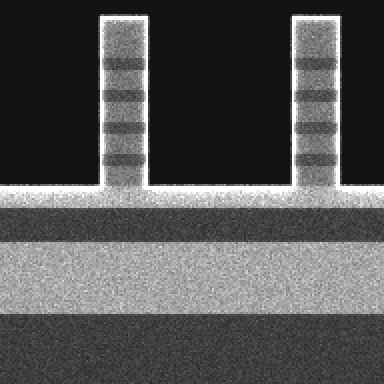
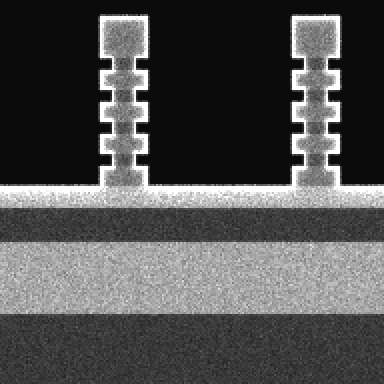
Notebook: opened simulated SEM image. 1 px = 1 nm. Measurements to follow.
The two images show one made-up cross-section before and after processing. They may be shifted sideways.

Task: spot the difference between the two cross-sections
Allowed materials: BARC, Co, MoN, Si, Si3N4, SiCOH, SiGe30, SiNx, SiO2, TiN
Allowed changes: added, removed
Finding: removed SiGe30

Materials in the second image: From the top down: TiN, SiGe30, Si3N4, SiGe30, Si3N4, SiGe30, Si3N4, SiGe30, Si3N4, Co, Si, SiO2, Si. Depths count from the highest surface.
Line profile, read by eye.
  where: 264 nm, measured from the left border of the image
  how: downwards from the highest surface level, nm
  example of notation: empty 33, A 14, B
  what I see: empty 170, Co 22, Si 34, SiO2 72, Si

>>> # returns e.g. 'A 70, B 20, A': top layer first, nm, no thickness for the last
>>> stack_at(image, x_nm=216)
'empty 170, Co 22, Si 34, SiO2 72, Si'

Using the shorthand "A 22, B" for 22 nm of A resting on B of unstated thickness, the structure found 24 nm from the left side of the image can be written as empty 170, Co 22, Si 34, SiO2 72, Si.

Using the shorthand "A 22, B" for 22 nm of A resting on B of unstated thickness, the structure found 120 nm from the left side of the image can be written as TiN 42, SiGe30 12, Si3N4 20, SiGe30 12, Si3N4 20, SiGe30 12, Si3N4 20, SiGe30 12, Si3N4 20, Co 22, Si 34, SiO2 72, Si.